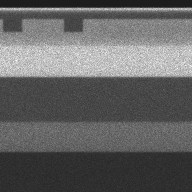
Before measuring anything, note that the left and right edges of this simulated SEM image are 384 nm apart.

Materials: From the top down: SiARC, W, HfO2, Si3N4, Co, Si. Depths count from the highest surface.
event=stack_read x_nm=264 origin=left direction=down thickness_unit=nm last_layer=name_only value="SiARC 22, W 54, HfO2 62, Si3N4 90, Co 60, Si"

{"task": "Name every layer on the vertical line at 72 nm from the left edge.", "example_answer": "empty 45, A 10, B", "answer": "SiARC 22, W 54, HfO2 62, Si3N4 90, Co 60, Si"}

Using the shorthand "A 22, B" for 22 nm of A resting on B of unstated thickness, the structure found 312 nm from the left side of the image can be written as SiARC 22, W 54, HfO2 62, Si3N4 90, Co 60, Si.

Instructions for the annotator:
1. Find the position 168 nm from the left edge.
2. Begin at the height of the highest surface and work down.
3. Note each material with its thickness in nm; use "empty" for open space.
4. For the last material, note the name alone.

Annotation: SiARC 22, W 54, HfO2 62, Si3N4 90, Co 60, Si